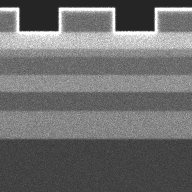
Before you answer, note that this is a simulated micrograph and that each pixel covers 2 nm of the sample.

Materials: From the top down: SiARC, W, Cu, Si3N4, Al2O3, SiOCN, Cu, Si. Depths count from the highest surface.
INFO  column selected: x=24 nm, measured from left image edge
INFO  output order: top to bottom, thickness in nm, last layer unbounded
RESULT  SiARC 48, W 34, Cu 16, Si3N4 36, Al2O3 34, SiOCN 38, Cu 56, Si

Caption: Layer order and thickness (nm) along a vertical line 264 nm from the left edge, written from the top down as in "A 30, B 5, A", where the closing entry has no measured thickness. empty 48, W 34, Cu 16, Si3N4 36, Al2O3 34, SiOCN 38, Cu 56, Si